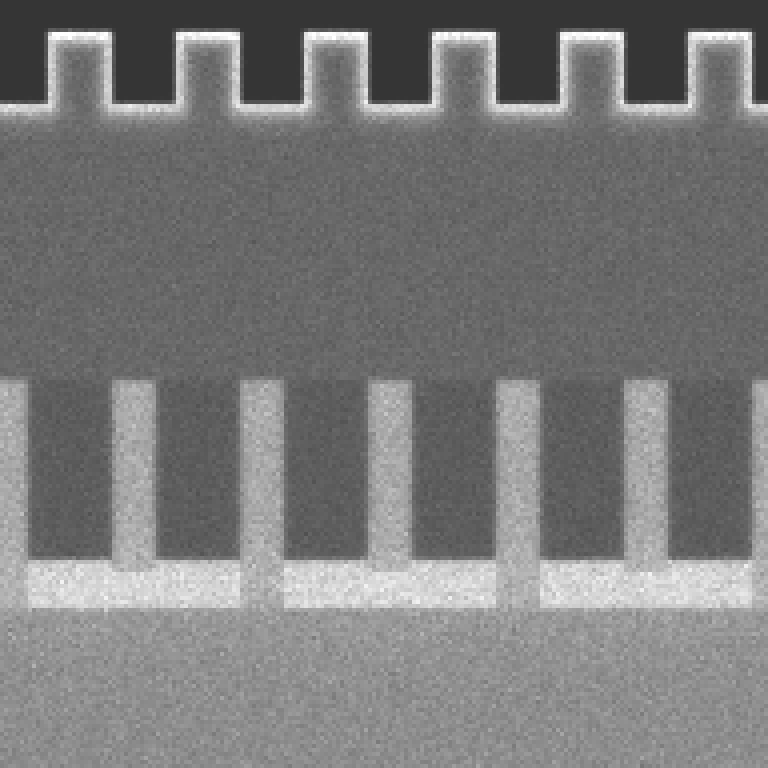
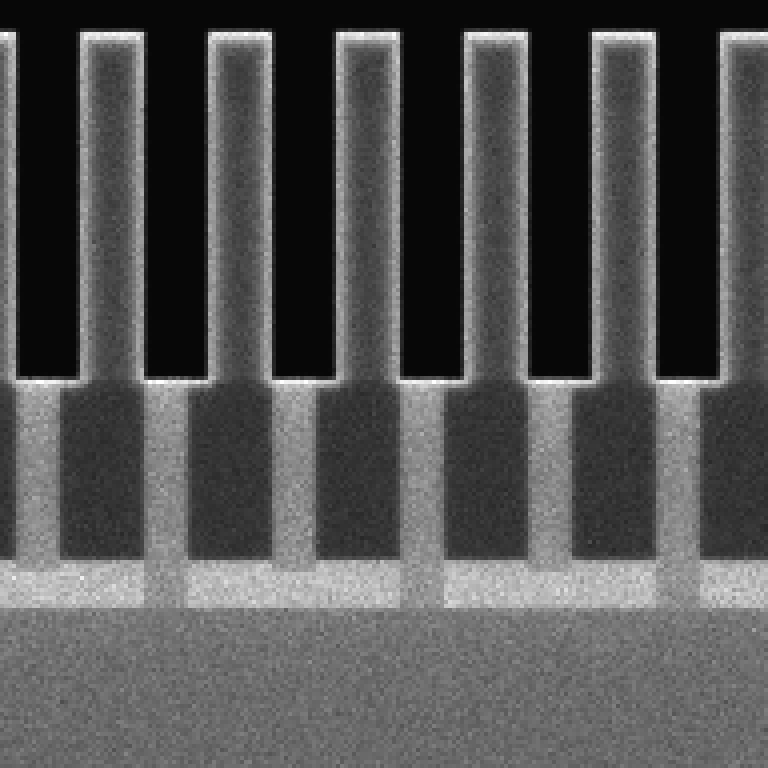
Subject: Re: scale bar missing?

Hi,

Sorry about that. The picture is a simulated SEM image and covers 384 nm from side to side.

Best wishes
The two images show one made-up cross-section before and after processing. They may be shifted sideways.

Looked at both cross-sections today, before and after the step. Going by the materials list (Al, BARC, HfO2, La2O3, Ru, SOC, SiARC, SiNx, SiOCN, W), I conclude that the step removed SOC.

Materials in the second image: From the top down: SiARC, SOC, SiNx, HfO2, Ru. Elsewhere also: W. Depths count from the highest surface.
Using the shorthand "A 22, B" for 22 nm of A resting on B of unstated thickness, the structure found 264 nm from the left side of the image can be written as empty 174, W 96, HfO2 18, Ru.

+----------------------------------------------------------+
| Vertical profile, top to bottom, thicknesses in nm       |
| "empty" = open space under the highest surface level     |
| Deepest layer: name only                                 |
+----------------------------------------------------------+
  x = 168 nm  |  SiARC 36, SOC 138, SiNx 90, HfO2 24, Ru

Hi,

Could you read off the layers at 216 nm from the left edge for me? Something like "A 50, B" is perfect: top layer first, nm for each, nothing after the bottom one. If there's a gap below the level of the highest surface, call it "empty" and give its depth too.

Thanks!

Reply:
empty 174, W 114, Ru